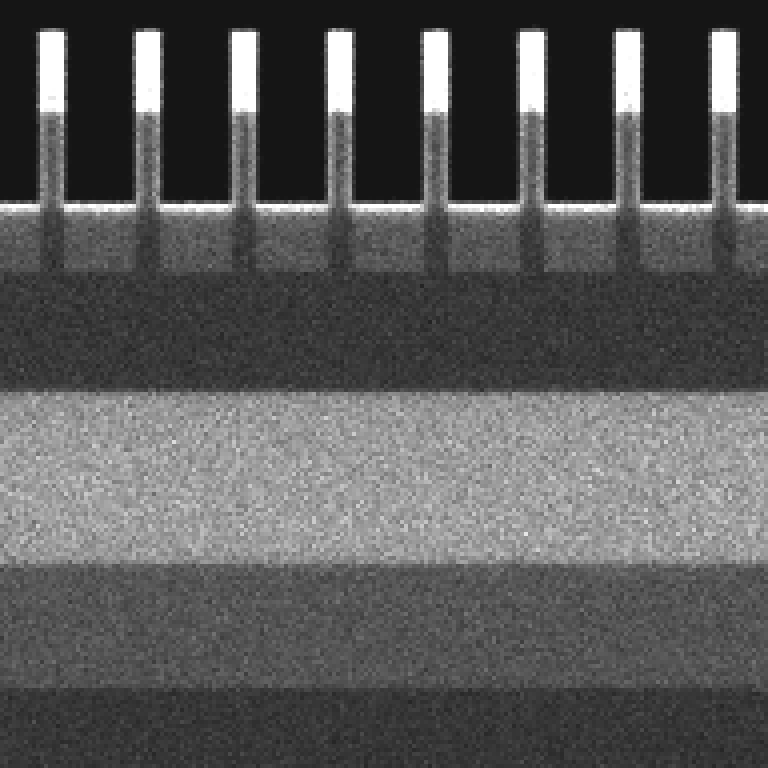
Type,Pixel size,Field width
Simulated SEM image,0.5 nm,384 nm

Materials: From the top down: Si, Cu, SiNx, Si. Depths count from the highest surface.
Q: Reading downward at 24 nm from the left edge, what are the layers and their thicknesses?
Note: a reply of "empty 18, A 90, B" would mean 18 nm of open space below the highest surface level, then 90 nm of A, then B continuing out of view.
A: Si 180, Cu 86, SiNx 62, Si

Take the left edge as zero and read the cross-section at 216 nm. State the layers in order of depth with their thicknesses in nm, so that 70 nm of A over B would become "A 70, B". Si 180, Cu 86, SiNx 62, Si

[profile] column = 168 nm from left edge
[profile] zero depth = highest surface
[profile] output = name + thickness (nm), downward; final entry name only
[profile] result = Si 180, Cu 86, SiNx 62, Si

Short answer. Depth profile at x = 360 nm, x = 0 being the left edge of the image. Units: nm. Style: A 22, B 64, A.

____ Si 180, Cu 86, SiNx 62, Si